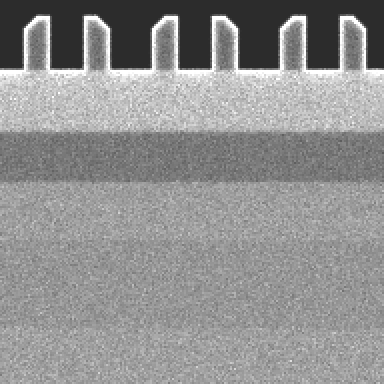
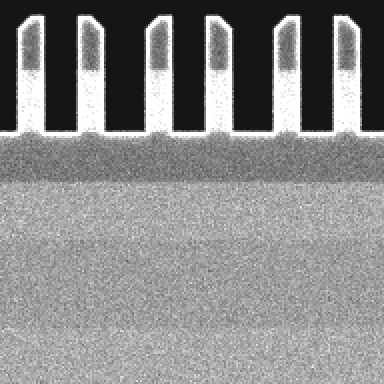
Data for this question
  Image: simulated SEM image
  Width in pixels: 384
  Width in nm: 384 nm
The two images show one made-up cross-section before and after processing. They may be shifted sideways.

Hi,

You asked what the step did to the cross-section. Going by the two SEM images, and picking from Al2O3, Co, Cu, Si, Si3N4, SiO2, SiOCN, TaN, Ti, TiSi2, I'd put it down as Co, removed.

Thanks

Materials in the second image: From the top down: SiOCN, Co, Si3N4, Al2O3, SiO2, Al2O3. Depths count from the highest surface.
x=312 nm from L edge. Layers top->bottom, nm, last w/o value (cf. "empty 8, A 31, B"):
empty 116, Si3N4 50, Al2O3 58, SiO2 88, Al2O3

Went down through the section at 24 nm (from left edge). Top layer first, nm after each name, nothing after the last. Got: empty 6, SiOCN 48, Co 62, Si3N4 50, Al2O3 58, SiO2 88, Al2O3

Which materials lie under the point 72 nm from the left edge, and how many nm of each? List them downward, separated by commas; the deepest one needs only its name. empty 116, Si3N4 50, Al2O3 58, SiO2 88, Al2O3